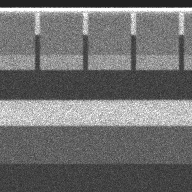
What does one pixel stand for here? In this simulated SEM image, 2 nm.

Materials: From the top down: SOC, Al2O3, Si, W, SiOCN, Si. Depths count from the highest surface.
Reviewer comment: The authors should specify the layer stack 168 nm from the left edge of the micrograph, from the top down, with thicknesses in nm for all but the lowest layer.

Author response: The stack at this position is SOC 10, W 44, Si 130, W 52, SiOCN 76, Si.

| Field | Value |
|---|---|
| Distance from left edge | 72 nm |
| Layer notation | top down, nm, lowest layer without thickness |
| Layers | SOC 10, W 44, Si 130, W 52, SiOCN 76, Si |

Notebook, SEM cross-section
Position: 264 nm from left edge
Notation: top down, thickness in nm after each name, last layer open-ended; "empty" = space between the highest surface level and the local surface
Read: SOC 10, W 44, Si 130, W 52, SiOCN 76, Si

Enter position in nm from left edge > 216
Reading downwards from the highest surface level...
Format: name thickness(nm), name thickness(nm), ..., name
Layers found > SOC 94, Al2O3 30, Si 60, W 52, SiOCN 76, Si